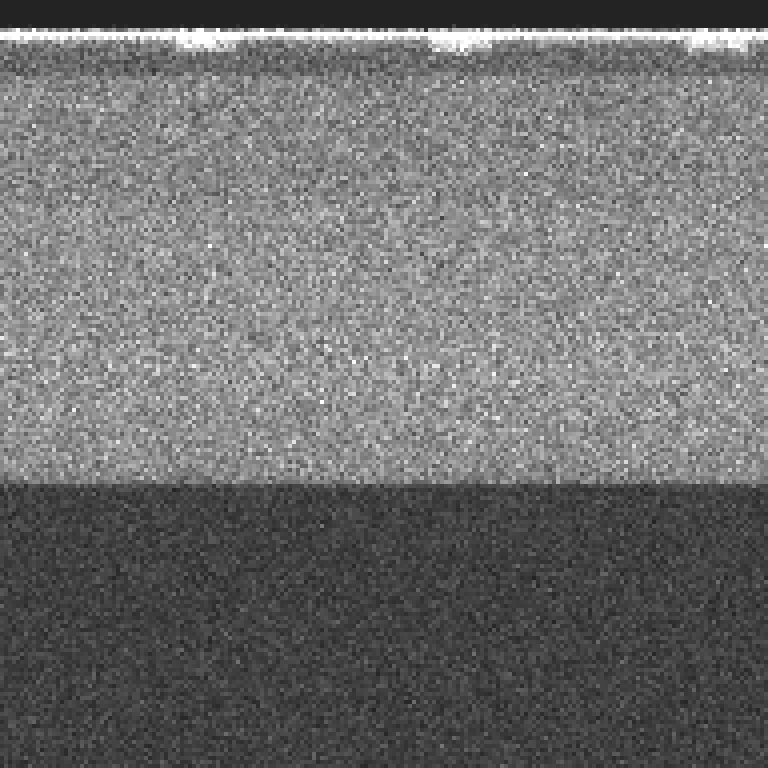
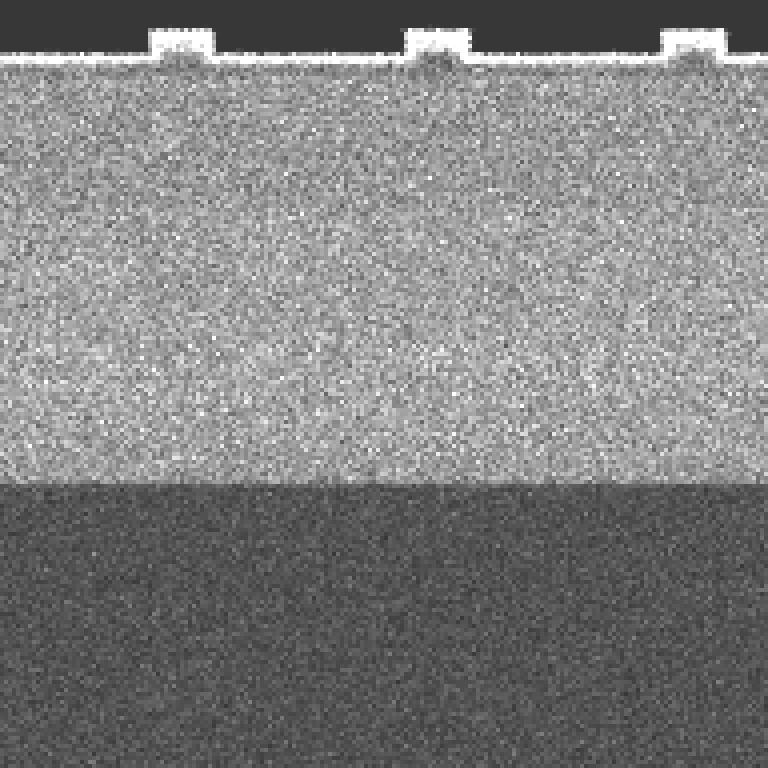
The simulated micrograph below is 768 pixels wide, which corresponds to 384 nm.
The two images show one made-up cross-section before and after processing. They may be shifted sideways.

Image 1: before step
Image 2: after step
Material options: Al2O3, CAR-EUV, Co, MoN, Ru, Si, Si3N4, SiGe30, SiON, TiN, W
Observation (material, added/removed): TiN, removed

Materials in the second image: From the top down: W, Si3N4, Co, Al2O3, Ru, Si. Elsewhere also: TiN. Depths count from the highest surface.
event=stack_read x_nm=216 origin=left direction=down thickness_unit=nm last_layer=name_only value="W 10, Si3N4 12, Co 66, Al2O3 64, Ru 74, Si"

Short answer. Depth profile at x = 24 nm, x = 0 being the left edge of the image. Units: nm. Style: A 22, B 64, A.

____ empty 12, TiN 10, Co 66, Al2O3 64, Ru 74, Si